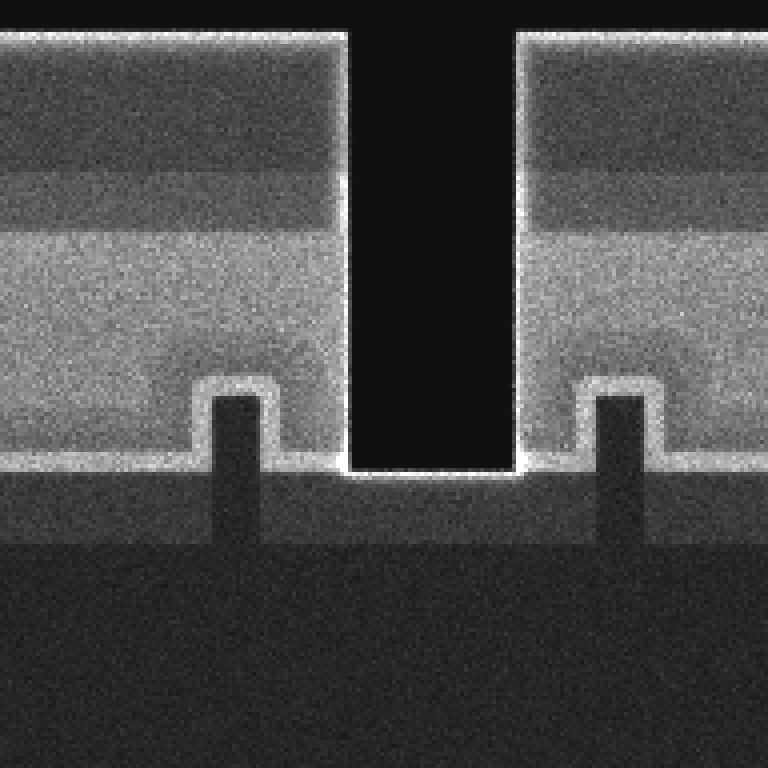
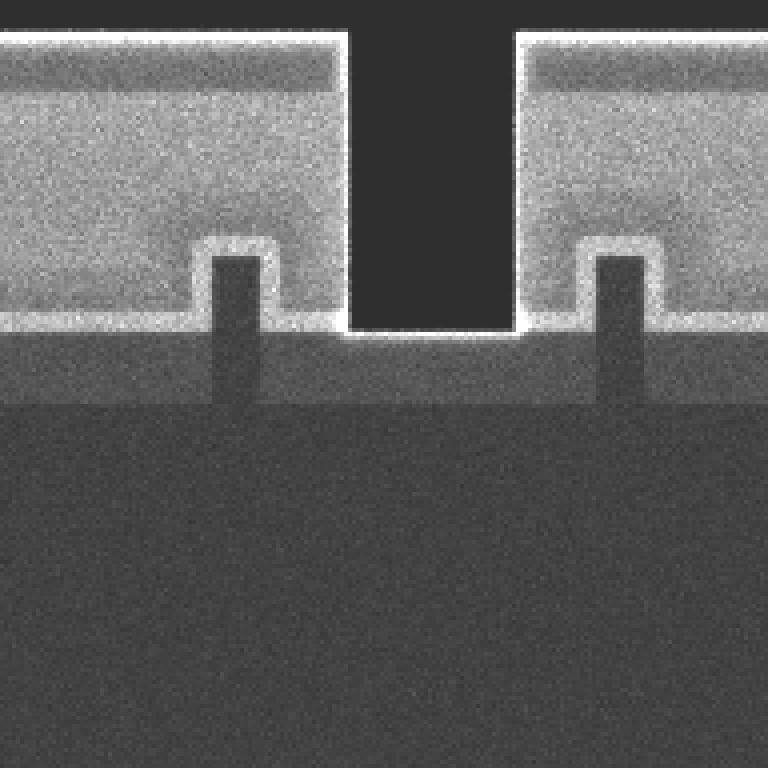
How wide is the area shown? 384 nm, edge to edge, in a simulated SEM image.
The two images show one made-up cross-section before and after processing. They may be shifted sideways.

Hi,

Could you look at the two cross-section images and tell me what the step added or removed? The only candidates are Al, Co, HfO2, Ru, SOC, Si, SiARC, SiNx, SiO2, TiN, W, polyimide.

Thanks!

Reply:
removed SOC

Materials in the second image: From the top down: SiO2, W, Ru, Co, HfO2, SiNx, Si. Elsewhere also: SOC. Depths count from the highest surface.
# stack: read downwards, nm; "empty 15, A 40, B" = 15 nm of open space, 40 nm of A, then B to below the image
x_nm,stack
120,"SiO2 30, W 50, Ru 12, Co 10, HfO2 10, Si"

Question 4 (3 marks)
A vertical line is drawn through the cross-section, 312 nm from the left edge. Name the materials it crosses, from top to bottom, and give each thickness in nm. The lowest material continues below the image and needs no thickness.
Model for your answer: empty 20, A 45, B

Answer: SiO2 30, W 50, Ru 12, Co 10, HfO2 10, Si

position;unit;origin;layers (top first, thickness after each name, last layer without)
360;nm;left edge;SiO2 30, W 88, Ru 12, Co 10, HfO2 10, SiNx 36, Si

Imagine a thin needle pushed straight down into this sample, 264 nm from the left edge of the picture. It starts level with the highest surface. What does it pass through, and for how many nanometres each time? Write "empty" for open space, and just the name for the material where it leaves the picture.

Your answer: SiO2 30, W 88, Ru 12, Co 10, HfO2 10, SiNx 36, Si